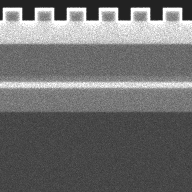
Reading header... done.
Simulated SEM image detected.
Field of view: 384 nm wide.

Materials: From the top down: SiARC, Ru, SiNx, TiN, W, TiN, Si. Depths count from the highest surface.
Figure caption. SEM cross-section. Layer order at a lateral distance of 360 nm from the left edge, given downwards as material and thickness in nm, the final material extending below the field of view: SiARC 26, Ru 46, SiNx 64, TiN 12, W 12, TiN 48, Si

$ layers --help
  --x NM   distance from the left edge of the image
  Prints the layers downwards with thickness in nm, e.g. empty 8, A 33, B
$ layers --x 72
SiARC 26, Ru 46, SiNx 64, TiN 12, W 12, TiN 48, Si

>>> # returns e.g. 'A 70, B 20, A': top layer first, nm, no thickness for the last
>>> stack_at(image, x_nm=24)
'SiARC 26, Ru 46, SiNx 64, TiN 12, W 12, TiN 48, Si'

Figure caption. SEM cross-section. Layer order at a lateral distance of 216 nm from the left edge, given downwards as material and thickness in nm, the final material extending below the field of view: SiARC 26, Ru 46, SiNx 64, TiN 12, W 12, TiN 48, Si